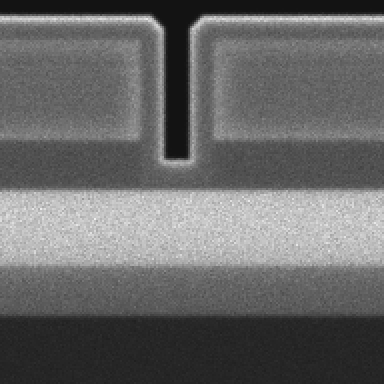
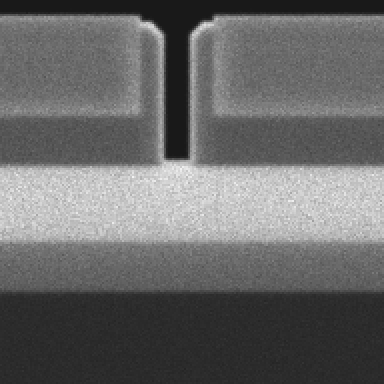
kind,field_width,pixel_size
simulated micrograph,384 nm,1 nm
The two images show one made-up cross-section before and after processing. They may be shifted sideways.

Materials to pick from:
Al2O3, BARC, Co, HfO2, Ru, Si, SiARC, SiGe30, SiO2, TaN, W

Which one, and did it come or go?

Al2O3 - removed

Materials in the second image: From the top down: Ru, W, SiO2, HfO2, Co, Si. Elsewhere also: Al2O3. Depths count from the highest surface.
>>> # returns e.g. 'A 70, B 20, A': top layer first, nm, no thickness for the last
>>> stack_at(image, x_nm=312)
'Ru 26, W 74, SiO2 50, HfO2 76, Co 50, Si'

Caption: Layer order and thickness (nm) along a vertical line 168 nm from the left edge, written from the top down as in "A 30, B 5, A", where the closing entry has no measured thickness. empty 144, SiO2 6, HfO2 76, Co 50, Si